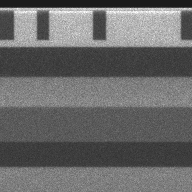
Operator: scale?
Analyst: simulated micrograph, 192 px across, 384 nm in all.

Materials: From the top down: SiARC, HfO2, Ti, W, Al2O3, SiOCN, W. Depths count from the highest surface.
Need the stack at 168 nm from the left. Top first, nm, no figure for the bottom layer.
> SiARC 6, HfO2 72, Ti 60, W 60, Al2O3 70, SiOCN 50, W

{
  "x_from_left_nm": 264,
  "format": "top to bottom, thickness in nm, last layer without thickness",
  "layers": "SiARC 6, HfO2 72, Ti 60, W 60, Al2O3 70, SiOCN 50, W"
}